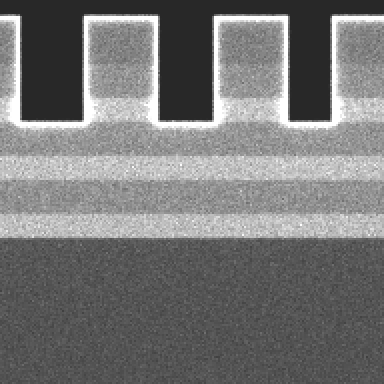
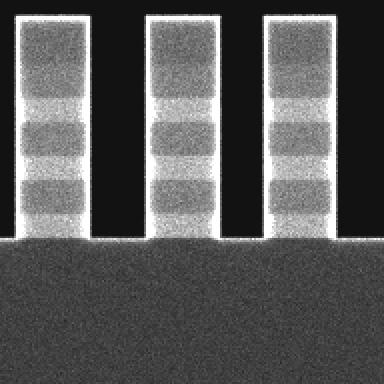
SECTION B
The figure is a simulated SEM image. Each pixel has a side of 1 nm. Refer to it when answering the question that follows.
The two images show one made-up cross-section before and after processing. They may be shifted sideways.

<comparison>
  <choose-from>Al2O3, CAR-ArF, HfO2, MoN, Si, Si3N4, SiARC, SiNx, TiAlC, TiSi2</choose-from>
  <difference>Al2O3 and Si3N4 removed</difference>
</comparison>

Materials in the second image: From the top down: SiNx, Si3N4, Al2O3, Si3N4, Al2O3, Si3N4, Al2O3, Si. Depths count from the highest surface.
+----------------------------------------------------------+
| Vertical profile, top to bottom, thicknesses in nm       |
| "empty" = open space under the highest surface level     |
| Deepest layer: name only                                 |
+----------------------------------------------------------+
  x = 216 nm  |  SiNx 48, Si3N4 34, Al2O3 24, Si3N4 34, Al2O3 24, Si3N4 34, Al2O3 24, Si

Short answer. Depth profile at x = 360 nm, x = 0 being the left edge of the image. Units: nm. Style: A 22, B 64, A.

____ empty 222, Si